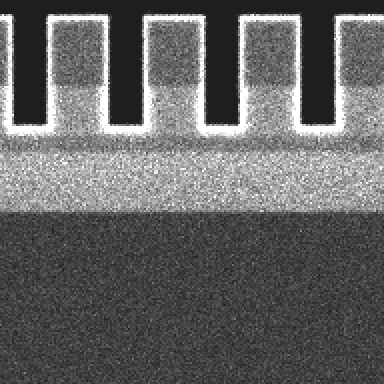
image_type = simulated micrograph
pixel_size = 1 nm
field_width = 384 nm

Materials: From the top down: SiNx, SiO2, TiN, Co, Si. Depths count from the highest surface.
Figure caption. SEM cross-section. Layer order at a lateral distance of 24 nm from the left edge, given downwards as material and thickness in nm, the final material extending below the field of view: empty 110, SiO2 10, TiN 16, Co 60, Si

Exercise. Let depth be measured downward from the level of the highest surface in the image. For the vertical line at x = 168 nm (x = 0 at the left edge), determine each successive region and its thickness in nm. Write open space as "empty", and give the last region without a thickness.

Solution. SiNx 70, SiO2 50, TiN 16, Co 60, Si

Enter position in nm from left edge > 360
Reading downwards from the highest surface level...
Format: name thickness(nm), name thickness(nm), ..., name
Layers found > SiNx 70, SiO2 50, TiN 16, Co 60, Si